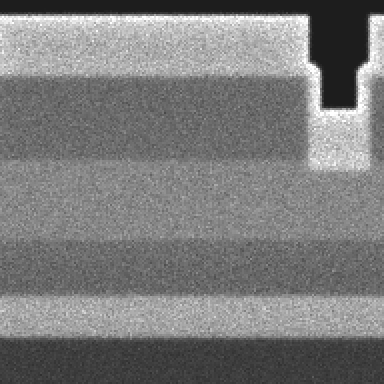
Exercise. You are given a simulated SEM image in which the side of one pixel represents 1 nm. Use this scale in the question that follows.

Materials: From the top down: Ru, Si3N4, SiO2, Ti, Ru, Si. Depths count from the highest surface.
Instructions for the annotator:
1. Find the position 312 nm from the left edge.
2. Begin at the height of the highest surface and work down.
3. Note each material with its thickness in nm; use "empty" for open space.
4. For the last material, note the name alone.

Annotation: empty 48, Ru 106, SiO2 70, Ti 56, Ru 42, Si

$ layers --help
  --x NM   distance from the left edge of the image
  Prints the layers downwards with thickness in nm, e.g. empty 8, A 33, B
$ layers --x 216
Ru 60, Si3N4 84, SiO2 80, Ti 56, Ru 42, Si